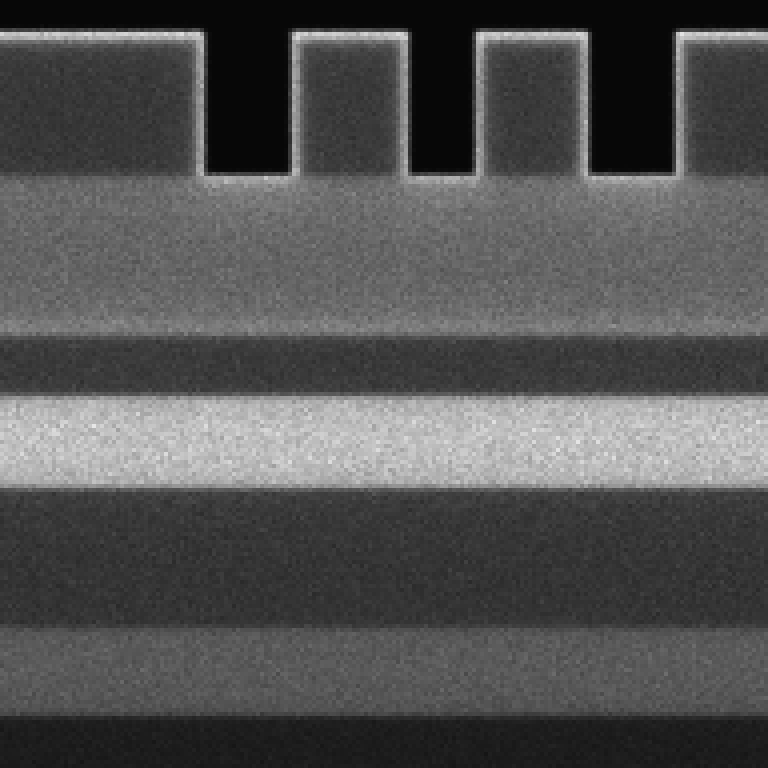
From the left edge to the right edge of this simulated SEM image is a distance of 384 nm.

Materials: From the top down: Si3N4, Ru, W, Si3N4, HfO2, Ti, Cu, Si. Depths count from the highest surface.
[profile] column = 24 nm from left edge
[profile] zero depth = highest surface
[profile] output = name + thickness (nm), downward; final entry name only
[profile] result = Si3N4 72, Ru 72, W 8, Si3N4 30, HfO2 46, Ti 70, Cu 44, Si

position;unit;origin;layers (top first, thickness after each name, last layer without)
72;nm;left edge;Si3N4 72, Ru 72, W 8, Si3N4 30, HfO2 46, Ti 70, Cu 44, Si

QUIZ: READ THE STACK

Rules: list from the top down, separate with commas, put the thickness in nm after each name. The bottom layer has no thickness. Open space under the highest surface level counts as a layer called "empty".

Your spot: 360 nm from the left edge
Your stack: Si3N4 72, Ru 72, W 8, Si3N4 30, HfO2 46, Ti 70, Cu 44, Si